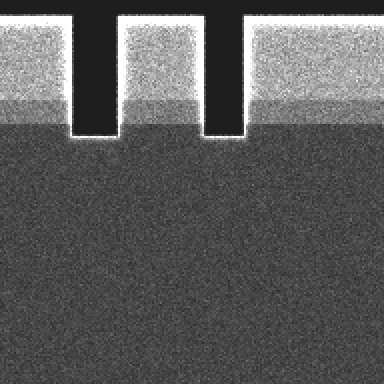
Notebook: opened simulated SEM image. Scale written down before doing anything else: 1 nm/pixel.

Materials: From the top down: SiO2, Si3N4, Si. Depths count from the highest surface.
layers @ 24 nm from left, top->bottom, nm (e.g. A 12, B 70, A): SiO2 84, Si3N4 24, Si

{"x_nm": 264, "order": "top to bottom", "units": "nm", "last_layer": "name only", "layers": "SiO2 84, Si3N4 24, Si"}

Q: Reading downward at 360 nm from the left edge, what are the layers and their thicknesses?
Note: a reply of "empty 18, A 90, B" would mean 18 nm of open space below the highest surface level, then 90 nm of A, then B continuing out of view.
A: SiO2 84, Si3N4 24, Si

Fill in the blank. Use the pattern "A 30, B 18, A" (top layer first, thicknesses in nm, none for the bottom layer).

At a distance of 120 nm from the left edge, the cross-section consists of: SiO2 84, Si3N4 24, Si